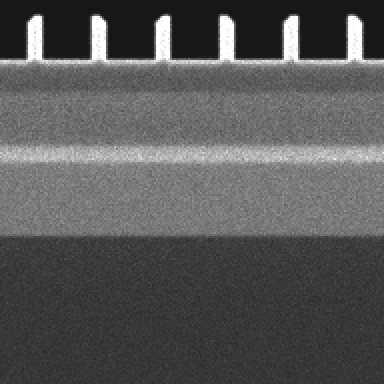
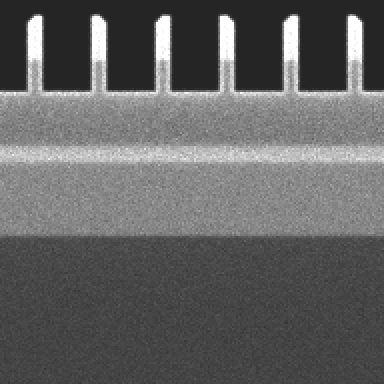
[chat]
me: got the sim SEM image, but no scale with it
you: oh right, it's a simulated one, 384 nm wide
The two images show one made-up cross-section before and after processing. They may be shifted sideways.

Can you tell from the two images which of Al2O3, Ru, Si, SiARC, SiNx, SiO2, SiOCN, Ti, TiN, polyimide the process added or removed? Yes, it removed SiNx.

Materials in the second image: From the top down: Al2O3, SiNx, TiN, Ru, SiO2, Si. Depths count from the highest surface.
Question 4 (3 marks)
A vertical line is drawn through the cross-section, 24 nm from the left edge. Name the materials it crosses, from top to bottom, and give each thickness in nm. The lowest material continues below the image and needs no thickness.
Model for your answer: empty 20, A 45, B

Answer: empty 76, TiN 54, Ru 16, SiO2 74, Si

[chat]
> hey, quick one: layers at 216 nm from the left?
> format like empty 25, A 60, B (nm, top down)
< empty 76, TiN 54, Ru 16, SiO2 74, Si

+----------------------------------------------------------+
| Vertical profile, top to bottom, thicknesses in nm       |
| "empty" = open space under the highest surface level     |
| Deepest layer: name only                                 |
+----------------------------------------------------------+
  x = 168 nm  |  Al2O3 44, SiNx 32, TiN 54, Ru 16, SiO2 74, Si